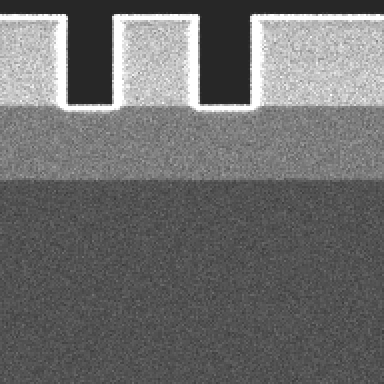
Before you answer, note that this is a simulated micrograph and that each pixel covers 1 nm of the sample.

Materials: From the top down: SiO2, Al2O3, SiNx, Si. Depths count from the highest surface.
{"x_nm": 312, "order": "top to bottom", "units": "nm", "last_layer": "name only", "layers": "SiO2 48, Al2O3 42, SiNx 74, Si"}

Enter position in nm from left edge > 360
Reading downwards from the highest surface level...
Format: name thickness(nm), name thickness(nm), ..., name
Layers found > SiO2 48, Al2O3 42, SiNx 74, Si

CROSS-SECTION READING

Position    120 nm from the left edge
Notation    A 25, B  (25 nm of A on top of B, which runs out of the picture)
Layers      SiO2 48, Al2O3 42, SiNx 74, Si